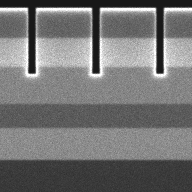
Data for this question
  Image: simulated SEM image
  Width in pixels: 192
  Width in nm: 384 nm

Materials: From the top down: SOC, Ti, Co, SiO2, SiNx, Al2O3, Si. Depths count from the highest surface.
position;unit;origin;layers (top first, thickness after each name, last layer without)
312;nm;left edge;empty 132, SiO2 60, SiNx 48, Al2O3 64, Si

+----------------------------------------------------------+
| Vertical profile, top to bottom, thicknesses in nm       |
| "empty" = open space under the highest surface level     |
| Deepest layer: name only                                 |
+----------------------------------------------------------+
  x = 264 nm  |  SOC 12, Ti 48, Co 58, SiO2 74, SiNx 48, Al2O3 64, Si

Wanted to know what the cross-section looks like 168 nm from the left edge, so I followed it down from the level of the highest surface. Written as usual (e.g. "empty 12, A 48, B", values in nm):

SOC 12, Ti 48, Co 58, SiO2 74, SiNx 48, Al2O3 64, Si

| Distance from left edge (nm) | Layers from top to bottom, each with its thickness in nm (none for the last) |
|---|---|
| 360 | SOC 12, Ti 48, Co 58, SiO2 74, SiNx 48, Al2O3 64, Si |